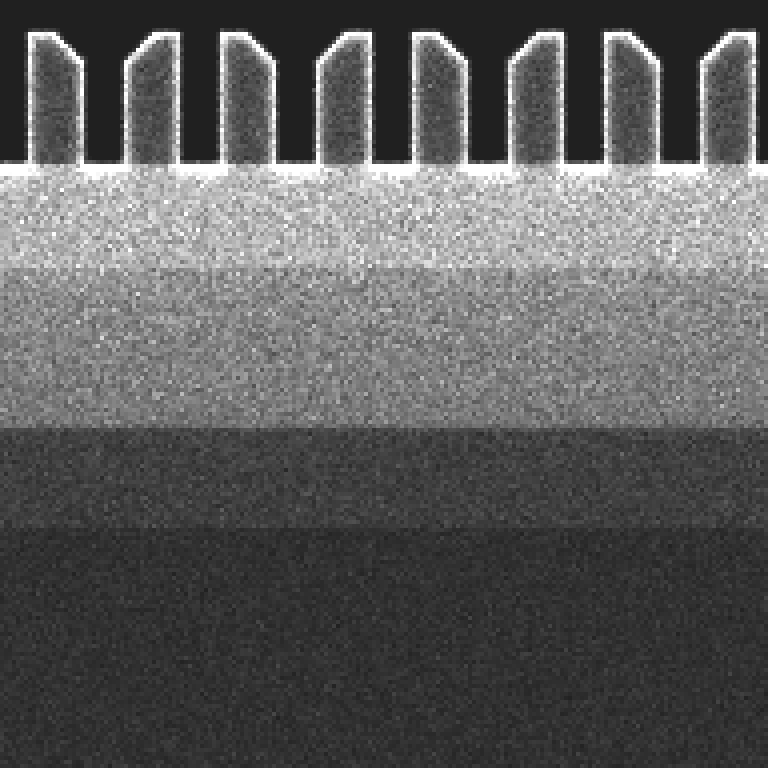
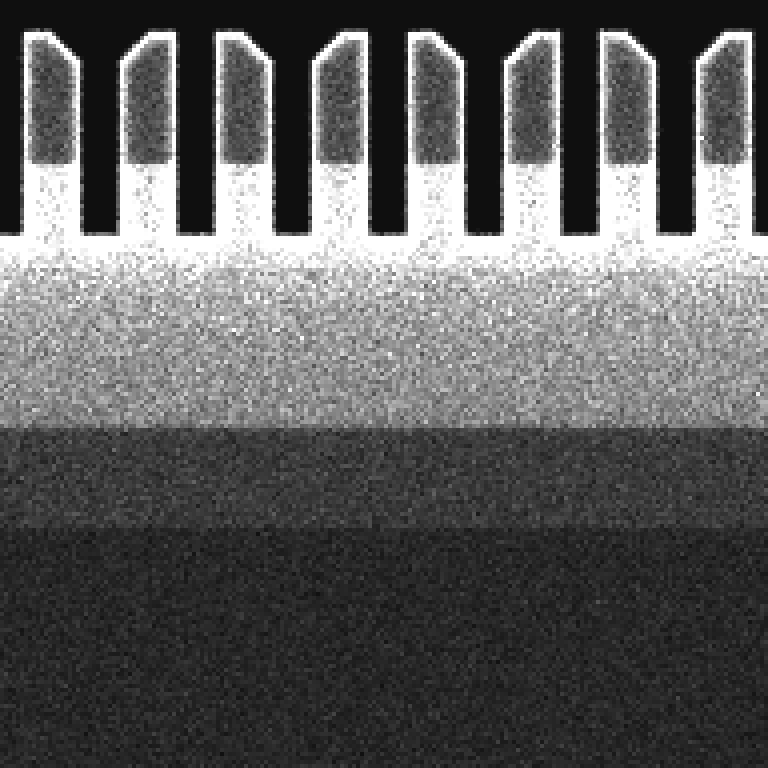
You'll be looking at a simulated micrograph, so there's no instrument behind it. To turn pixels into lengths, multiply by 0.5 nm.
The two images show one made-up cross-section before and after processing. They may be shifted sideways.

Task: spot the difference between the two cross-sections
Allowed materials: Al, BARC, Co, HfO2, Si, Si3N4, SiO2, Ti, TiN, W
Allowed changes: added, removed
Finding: removed HfO2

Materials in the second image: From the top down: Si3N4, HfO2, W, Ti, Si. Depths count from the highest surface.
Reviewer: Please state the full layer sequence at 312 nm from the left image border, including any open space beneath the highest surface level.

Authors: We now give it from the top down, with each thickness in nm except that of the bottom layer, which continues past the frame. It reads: Si3N4 66, HfO2 52, W 80, Ti 50, Si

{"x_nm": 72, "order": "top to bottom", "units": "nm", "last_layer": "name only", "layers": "empty 2, Si3N4 64, HfO2 52, W 80, Ti 50, Si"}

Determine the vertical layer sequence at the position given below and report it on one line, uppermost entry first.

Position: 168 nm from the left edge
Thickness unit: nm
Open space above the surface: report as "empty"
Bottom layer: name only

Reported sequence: empty 2, Si3N4 64, HfO2 52, W 80, Ti 50, Si